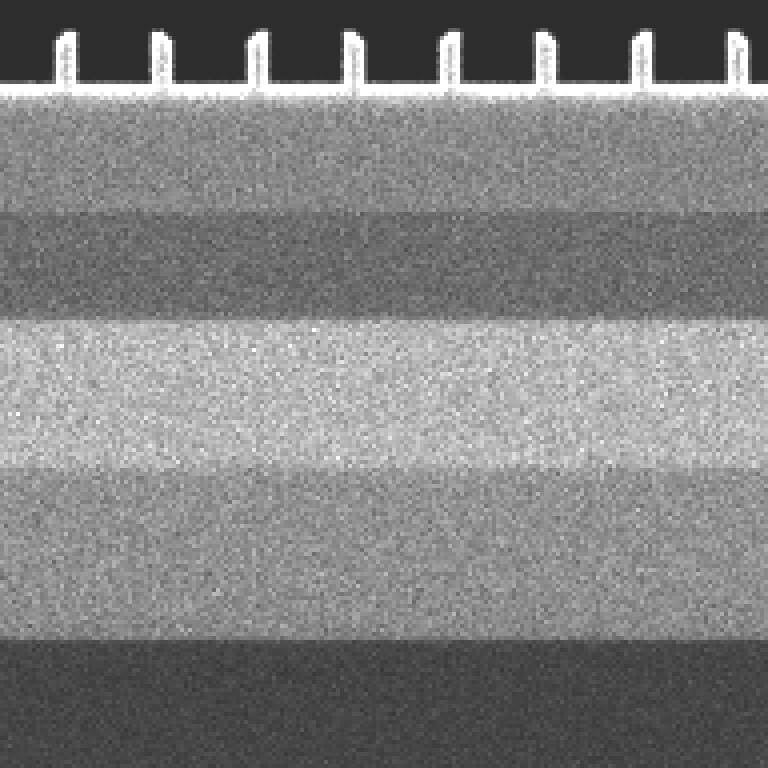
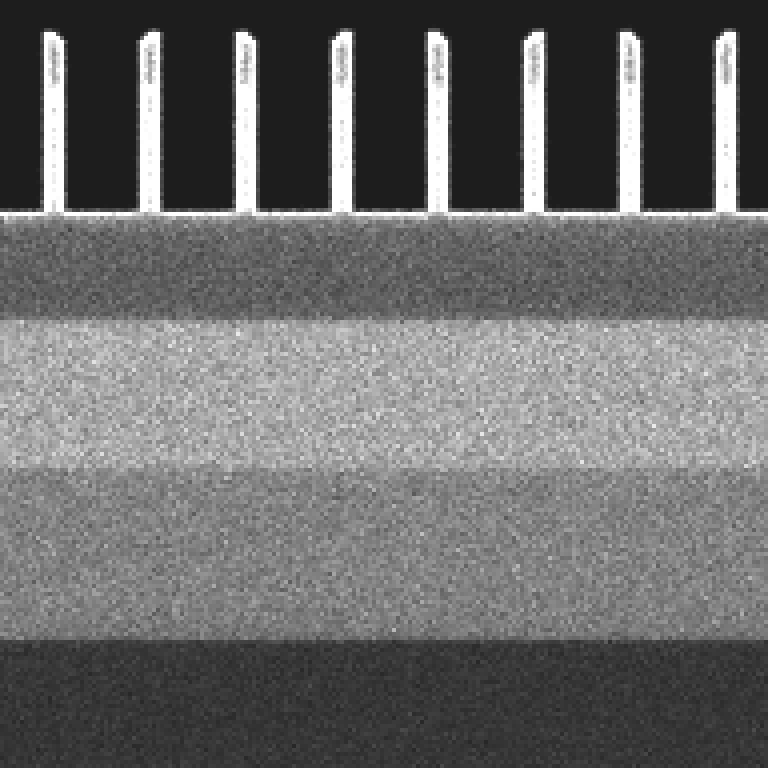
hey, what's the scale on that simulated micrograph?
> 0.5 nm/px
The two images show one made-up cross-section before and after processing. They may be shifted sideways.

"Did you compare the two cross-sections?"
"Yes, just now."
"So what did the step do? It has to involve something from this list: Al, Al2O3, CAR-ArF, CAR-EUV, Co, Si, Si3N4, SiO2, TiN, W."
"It removed Al2O3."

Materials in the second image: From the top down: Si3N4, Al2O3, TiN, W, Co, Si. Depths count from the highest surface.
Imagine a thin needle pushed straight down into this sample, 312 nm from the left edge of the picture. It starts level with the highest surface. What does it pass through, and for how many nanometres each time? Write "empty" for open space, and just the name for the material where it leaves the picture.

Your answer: Si3N4 26, Al2O3 64, TiN 54, W 74, Co 86, Si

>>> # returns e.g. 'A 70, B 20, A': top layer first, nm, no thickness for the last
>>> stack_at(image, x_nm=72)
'empty 2, Si3N4 24, Al2O3 64, TiN 54, W 74, Co 86, Si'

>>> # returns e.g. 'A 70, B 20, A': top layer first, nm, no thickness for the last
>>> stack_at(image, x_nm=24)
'Si3N4 26, Al2O3 64, TiN 54, W 74, Co 86, Si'